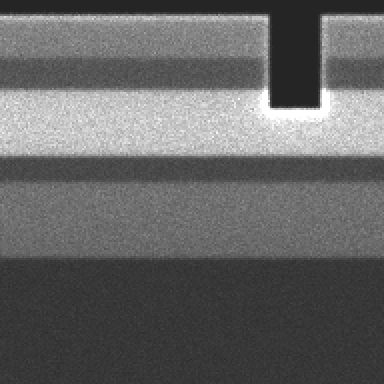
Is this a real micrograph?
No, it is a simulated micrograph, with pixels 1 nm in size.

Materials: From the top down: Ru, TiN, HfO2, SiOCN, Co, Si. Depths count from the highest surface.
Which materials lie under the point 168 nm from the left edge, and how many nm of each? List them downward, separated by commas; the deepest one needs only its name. Ru 42, TiN 32, HfO2 66, SiOCN 26, Co 76, Si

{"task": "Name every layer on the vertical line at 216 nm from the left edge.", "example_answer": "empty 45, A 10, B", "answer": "Ru 42, TiN 32, HfO2 66, SiOCN 26, Co 76, Si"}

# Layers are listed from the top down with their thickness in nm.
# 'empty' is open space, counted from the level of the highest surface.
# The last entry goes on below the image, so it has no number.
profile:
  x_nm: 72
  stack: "Ru 42, TiN 32, HfO2 66, SiOCN 26, Co 76, Si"